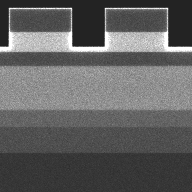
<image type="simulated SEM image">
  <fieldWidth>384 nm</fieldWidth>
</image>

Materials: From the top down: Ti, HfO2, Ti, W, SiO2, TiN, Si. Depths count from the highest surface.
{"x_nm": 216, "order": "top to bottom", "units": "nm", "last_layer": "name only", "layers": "Ti 48, HfO2 40, Ti 28, W 88, SiO2 34, TiN 52, Si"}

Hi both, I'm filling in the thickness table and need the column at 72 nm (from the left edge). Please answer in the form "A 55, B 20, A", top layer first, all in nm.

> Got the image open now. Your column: Ti 48, HfO2 40, Ti 28, W 88, SiO2 34, TiN 52, Si